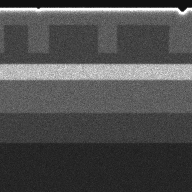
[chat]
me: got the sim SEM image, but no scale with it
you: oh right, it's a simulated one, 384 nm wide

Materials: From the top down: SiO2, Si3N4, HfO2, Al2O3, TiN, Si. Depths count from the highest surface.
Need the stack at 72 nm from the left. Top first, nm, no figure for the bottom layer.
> SiO2 90, Si3N4 22, HfO2 32, Al2O3 66, TiN 60, Si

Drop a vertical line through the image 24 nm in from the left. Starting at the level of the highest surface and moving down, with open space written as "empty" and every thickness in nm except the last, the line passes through SiO2 34, Si3N4 78, HfO2 32, Al2O3 66, TiN 60, Si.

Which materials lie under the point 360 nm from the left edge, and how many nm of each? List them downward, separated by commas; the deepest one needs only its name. empty 6, SiO2 84, Si3N4 22, HfO2 32, Al2O3 66, TiN 60, Si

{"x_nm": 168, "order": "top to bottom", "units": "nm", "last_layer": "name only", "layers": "SiO2 34, Si3N4 78, HfO2 32, Al2O3 66, TiN 60, Si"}